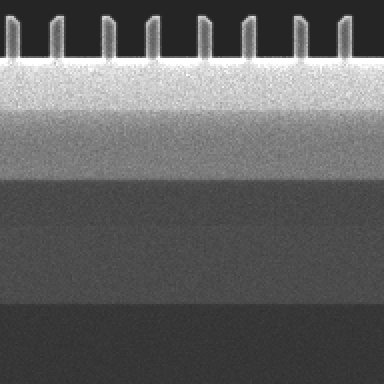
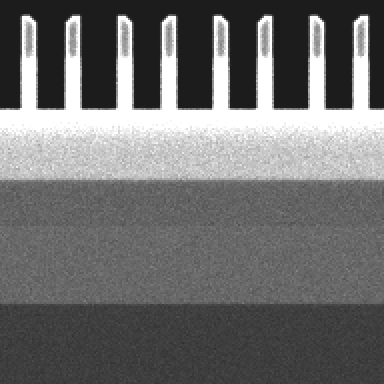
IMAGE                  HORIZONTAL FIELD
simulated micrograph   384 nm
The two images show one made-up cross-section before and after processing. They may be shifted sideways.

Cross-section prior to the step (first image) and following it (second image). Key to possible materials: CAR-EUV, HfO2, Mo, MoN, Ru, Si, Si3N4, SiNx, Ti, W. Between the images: HfO2 was removed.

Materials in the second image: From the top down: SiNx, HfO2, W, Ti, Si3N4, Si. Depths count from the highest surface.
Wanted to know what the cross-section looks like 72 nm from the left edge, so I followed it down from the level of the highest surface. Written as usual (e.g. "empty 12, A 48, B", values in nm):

SiNx 42, HfO2 52, W 70, Ti 46, Si3N4 78, Si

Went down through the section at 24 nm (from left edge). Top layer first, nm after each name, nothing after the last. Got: SiNx 42, HfO2 52, W 70, Ti 46, Si3N4 78, Si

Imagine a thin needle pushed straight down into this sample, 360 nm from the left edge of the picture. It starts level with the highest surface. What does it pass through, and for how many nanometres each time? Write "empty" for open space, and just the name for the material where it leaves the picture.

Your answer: SiNx 42, HfO2 52, W 70, Ti 46, Si3N4 78, Si